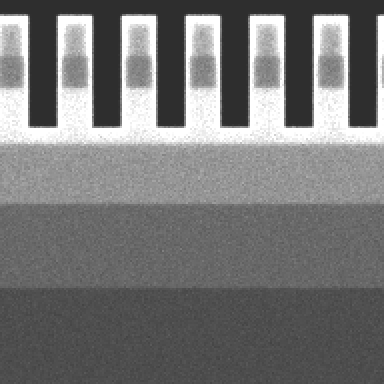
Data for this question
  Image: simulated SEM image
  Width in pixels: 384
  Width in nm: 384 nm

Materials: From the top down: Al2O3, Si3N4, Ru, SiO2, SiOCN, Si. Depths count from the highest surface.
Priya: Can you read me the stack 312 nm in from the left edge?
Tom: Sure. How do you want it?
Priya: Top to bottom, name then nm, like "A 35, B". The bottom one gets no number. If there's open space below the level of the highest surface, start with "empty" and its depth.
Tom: empty 112, Ru 16, SiO2 60, SiOCN 84, Si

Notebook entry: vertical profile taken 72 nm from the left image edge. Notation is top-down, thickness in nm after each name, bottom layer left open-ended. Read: Al2O3 40, Si3N4 32, Ru 56, SiO2 60, SiOCN 84, Si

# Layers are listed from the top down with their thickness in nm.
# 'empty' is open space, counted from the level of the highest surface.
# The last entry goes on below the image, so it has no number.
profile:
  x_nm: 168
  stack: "empty 112, Ru 16, SiO2 60, SiOCN 84, Si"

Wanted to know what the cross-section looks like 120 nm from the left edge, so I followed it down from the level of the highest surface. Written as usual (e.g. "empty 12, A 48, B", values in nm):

empty 112, Ru 16, SiO2 60, SiOCN 84, Si